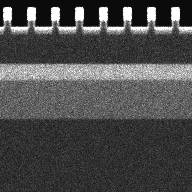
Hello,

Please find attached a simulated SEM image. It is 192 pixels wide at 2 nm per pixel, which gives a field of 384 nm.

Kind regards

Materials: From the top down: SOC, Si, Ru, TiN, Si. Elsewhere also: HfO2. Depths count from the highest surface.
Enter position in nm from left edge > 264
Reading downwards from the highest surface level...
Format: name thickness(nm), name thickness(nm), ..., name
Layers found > empty 38, SOC 14, Si 60, Ru 32, TiN 78, Si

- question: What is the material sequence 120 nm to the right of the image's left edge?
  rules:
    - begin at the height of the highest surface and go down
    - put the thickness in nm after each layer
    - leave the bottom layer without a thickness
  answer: empty 38, SOC 14, Si 60, Ru 32, TiN 78, Si